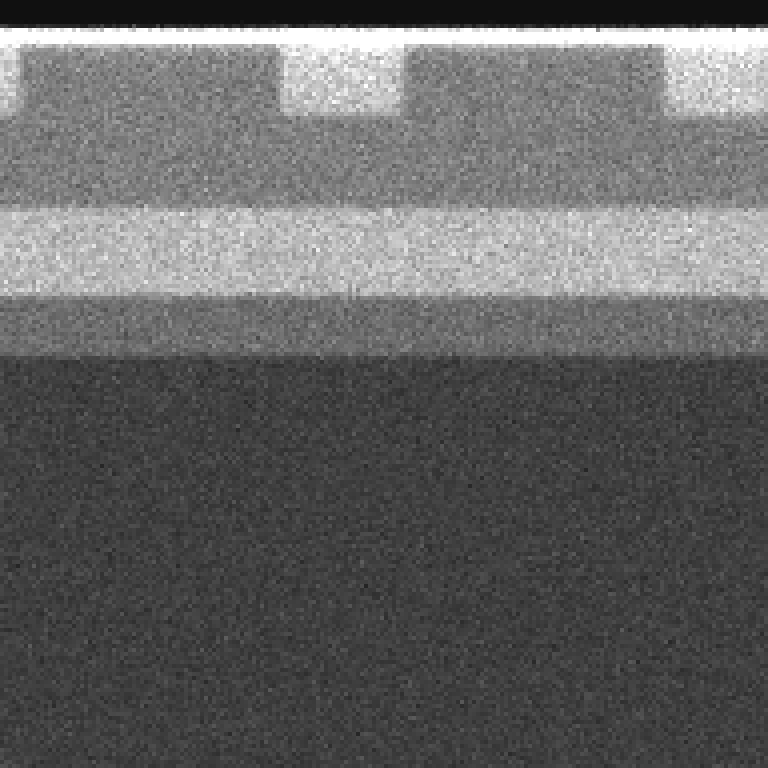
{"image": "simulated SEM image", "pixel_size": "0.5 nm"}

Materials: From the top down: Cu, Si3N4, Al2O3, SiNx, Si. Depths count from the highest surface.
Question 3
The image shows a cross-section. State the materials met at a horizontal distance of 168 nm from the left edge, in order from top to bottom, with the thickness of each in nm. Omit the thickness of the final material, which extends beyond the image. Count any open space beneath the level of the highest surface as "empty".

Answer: Cu 42, Si3N4 46, Al2O3 44, SiNx 30, Si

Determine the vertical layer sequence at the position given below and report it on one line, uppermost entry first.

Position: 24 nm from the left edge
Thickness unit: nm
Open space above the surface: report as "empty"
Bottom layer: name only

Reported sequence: Si3N4 88, Al2O3 44, SiNx 30, Si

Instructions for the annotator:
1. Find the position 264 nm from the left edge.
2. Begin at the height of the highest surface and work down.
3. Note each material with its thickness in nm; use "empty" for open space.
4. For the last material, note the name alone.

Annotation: Si3N4 88, Al2O3 44, SiNx 30, Si